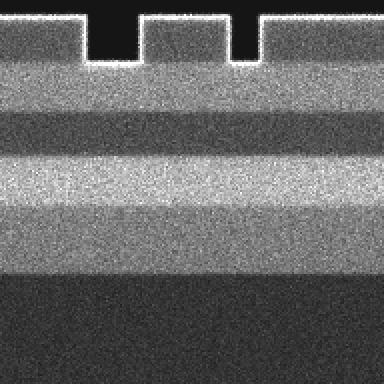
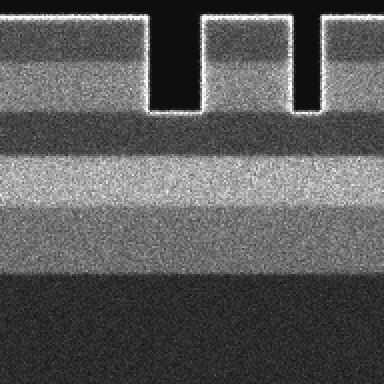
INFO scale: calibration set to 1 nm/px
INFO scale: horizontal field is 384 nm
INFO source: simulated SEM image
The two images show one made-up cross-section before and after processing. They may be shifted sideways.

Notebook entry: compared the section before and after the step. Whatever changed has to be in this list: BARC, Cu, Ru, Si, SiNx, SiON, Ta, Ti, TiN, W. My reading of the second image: Ru removed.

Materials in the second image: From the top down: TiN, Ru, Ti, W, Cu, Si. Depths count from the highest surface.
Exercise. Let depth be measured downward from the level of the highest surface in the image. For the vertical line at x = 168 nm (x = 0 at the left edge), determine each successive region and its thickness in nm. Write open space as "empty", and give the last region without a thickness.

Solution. empty 96, Ti 44, W 50, Cu 68, Si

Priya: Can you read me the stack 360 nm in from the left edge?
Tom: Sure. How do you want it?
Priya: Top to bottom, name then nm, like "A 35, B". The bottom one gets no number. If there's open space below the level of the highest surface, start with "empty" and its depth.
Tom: TiN 46, Ru 50, Ti 44, W 50, Cu 68, Si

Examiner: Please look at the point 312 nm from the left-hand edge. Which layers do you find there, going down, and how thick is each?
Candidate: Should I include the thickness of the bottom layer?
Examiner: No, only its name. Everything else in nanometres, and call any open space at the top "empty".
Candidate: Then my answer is empty 96, Ti 44, W 50, Cu 68, Si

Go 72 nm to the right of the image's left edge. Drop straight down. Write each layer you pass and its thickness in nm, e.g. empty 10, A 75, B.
TiN 46, Ru 50, Ti 44, W 50, Cu 68, Si